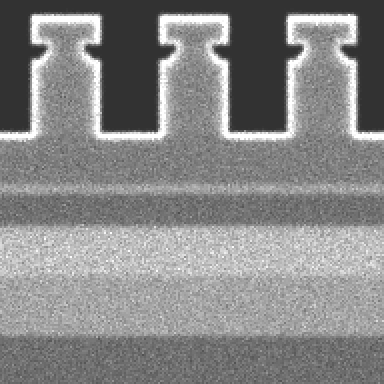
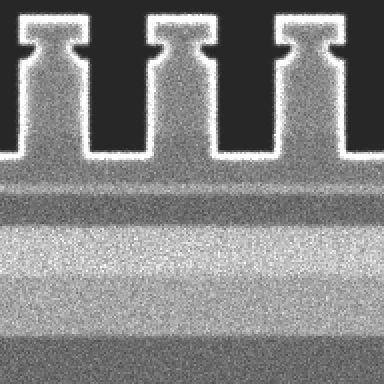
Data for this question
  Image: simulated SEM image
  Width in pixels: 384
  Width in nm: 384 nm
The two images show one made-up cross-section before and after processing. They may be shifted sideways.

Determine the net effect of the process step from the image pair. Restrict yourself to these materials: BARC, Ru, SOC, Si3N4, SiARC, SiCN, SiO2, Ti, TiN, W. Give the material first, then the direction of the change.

Si3N4: removed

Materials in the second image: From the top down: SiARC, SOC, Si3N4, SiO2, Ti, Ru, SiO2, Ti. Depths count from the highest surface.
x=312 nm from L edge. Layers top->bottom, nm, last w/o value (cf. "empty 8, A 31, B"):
SiARC 28, SOC 90, Si3N4 50, SiO2 10, Ti 32, Ru 50, SiO2 60, Ti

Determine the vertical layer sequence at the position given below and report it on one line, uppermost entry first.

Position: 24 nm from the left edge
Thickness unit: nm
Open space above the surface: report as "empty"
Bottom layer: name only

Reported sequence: SiARC 28, empty 16, SOC 74, Si3N4 50, SiO2 10, Ti 32, Ru 50, SiO2 60, Ti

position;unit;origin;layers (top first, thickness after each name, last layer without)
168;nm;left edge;SiARC 28, SOC 90, Si3N4 50, SiO2 10, Ti 32, Ru 50, SiO2 60, Ti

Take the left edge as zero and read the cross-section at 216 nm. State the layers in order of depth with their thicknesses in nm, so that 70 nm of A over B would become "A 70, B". empty 138, Si3N4 30, SiO2 10, Ti 32, Ru 50, SiO2 60, Ti